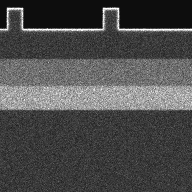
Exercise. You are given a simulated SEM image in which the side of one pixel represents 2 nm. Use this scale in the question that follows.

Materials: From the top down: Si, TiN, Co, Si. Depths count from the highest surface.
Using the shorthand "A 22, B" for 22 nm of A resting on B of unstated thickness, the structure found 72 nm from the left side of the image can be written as empty 42, Si 60, TiN 54, Co 48, Si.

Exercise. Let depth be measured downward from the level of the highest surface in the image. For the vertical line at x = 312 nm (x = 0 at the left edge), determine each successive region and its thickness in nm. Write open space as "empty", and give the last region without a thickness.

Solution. empty 42, Si 60, TiN 54, Co 48, Si